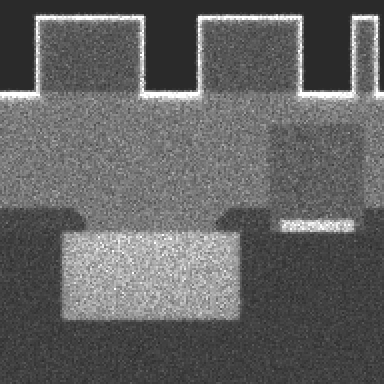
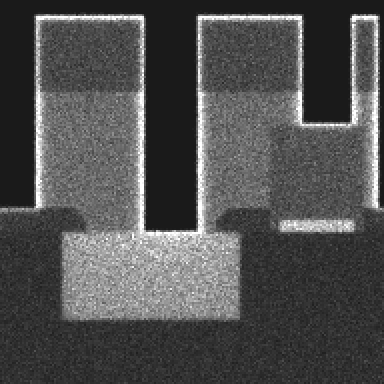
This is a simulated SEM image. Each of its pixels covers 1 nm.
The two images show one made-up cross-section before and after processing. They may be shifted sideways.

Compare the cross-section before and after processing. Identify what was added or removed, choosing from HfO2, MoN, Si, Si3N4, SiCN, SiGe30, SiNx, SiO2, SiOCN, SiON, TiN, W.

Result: SiO2 removed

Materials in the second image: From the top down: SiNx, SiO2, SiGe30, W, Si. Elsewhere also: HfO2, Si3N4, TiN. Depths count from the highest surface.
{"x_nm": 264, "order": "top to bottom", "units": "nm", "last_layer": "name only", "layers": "SiNx 76, SiO2 116, SiGe30 24, Si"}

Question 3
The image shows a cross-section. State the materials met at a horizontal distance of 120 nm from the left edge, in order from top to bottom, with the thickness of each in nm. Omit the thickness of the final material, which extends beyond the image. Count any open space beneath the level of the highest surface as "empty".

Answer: SiNx 76, SiO2 140, W 88, Si